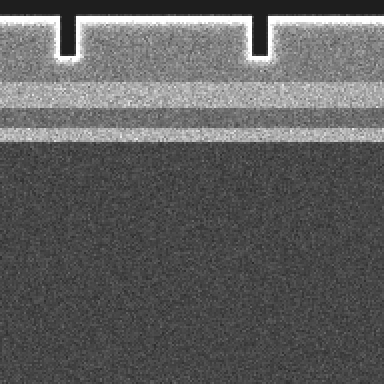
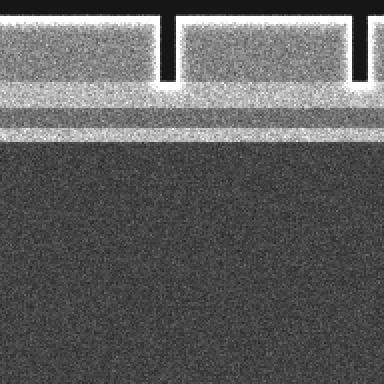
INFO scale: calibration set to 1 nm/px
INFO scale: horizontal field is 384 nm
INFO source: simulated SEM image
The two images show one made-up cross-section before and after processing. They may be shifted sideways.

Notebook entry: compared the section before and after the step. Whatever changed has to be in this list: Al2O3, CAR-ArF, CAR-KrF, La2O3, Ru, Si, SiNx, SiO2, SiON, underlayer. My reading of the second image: underlayer removed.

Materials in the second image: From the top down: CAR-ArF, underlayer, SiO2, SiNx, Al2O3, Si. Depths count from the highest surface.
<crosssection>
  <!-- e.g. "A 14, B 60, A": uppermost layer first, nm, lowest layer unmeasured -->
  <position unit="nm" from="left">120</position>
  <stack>CAR-ArF 40, underlayer 26, SiO2 26, SiNx 20, Al2O3 14, Si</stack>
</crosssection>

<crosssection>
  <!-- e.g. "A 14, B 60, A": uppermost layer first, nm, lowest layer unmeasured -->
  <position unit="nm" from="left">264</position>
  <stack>CAR-ArF 40, underlayer 26, SiO2 26, SiNx 20, Al2O3 14, Si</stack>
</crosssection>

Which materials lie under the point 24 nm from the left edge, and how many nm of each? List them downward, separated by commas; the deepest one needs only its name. CAR-ArF 40, underlayer 26, SiO2 26, SiNx 20, Al2O3 14, Si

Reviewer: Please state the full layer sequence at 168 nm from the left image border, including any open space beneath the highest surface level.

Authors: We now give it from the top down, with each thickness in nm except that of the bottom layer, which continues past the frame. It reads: empty 66, SiO2 26, SiNx 20, Al2O3 14, Si